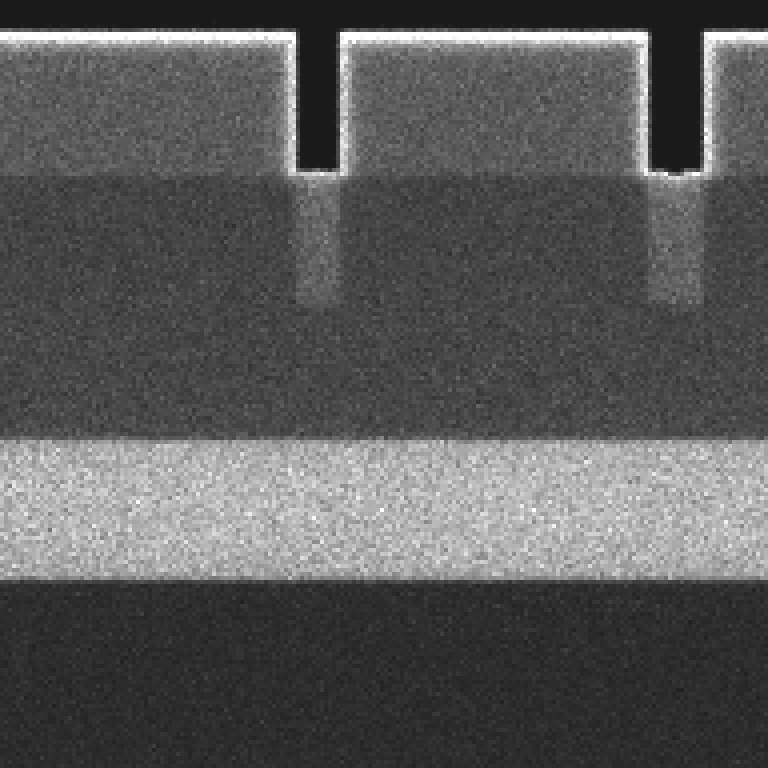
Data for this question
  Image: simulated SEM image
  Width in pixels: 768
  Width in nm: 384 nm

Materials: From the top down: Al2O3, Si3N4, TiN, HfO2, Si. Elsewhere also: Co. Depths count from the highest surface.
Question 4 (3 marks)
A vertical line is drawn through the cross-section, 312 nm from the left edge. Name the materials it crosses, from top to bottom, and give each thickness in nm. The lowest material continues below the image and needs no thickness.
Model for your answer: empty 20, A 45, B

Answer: Al2O3 72, Si3N4 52, TiN 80, HfO2 70, Si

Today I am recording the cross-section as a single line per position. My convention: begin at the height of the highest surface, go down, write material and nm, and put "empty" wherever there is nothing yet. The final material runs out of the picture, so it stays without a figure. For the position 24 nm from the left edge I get Al2O3 72, Si3N4 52, TiN 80, HfO2 70, Si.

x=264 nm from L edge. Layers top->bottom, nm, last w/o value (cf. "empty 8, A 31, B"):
Al2O3 72, Si3N4 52, TiN 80, HfO2 70, Si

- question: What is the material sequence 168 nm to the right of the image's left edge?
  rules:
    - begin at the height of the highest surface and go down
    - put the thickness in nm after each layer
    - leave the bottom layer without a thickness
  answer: empty 70, Co 66, TiN 68, HfO2 70, Si